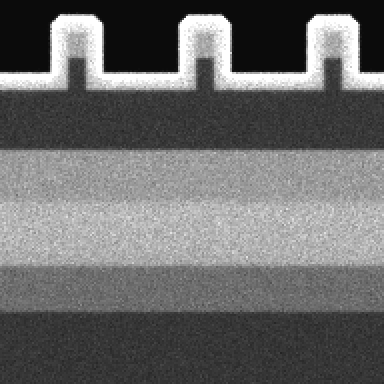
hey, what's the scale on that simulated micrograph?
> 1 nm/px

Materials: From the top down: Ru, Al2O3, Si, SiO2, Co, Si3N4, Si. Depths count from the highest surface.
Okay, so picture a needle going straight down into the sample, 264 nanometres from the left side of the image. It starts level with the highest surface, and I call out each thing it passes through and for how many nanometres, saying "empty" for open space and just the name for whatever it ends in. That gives empty 58, Ru 16, Si 60, SiO2 52, Co 64, Si3N4 46, Si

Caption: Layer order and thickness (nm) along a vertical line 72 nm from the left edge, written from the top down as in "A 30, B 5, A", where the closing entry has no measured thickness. Ru 16, Al2O3 26, Si 92, SiO2 52, Co 64, Si3N4 46, Si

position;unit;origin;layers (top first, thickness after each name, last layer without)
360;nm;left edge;empty 58, Ru 16, Si 60, SiO2 52, Co 64, Si3N4 46, Si